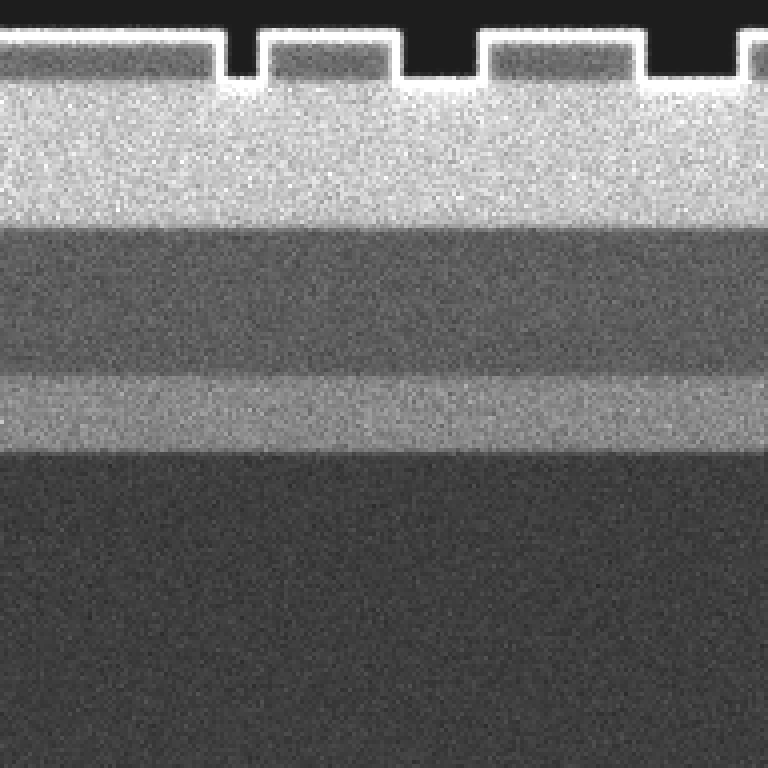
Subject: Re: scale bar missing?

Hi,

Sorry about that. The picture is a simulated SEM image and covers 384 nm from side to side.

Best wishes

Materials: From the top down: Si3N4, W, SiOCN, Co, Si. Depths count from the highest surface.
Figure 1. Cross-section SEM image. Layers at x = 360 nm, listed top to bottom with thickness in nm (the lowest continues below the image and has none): empty 24, W 74, SiOCN 74, Co 38, Si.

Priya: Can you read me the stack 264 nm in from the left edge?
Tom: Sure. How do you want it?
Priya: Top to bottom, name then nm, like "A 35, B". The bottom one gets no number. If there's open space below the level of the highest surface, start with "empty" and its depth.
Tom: Si3N4 24, W 74, SiOCN 74, Co 38, Si